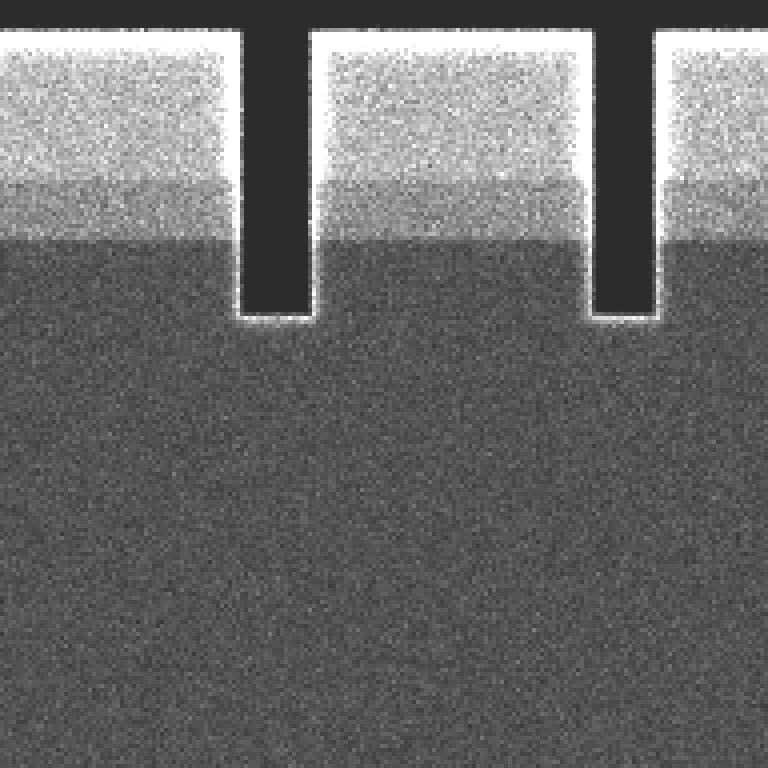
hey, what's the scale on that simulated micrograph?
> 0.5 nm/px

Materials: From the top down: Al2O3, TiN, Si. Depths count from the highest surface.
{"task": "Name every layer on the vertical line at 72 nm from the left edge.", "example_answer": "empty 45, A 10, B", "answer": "Al2O3 74, TiN 30, Si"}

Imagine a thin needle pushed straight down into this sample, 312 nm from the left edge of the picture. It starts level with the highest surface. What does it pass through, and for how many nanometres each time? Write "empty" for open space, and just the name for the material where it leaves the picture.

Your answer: empty 142, Si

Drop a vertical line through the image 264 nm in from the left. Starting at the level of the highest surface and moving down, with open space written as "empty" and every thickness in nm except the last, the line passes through Al2O3 74, TiN 30, Si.